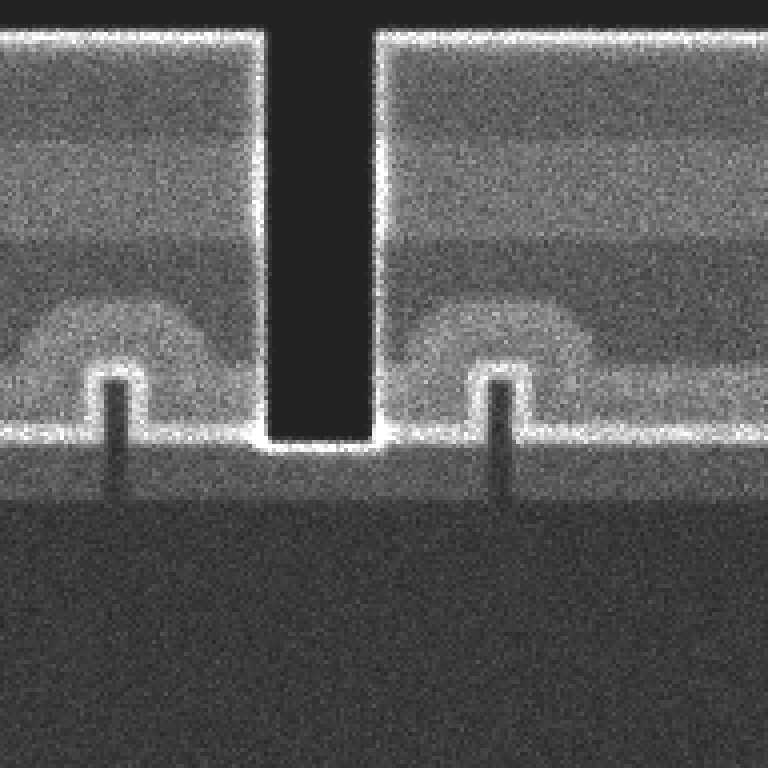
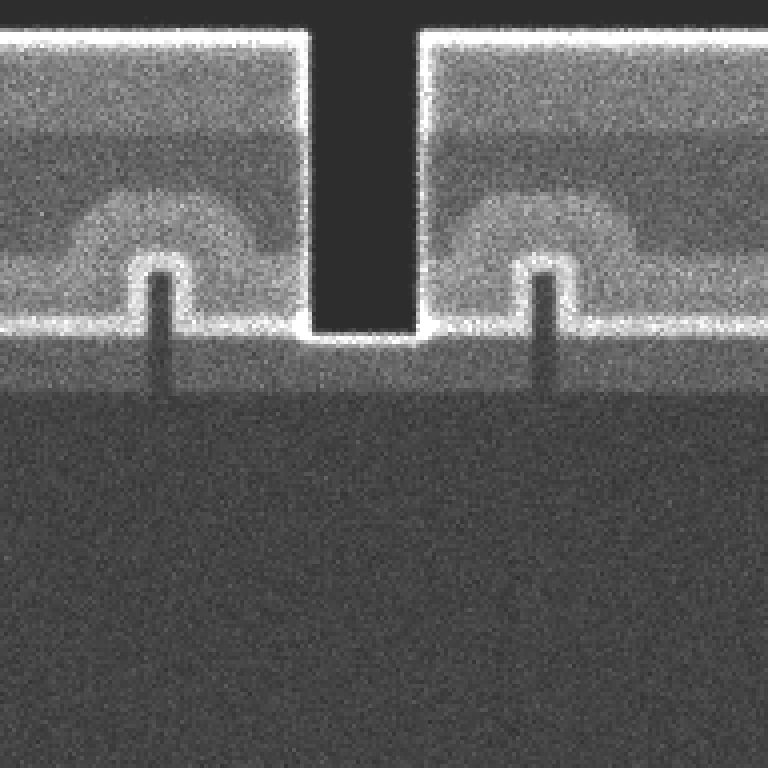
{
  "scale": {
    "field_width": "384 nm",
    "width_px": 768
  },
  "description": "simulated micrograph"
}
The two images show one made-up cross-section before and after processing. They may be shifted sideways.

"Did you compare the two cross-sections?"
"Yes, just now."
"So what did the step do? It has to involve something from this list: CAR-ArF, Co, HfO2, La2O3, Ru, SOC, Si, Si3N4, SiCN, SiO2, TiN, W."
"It removed SOC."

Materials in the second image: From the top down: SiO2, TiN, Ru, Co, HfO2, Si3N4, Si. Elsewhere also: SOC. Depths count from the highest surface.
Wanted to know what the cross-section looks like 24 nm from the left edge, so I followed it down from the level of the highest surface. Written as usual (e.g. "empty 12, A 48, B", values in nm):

SiO2 50, TiN 62, Ru 16, Co 14, HfO2 10, Si3N4 28, Si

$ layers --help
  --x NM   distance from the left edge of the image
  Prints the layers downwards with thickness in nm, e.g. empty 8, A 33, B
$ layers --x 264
SiO2 50, TiN 30, Ru 16, Co 14, HfO2 42, Si3N4 28, Si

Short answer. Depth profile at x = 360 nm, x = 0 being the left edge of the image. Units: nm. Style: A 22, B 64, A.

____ SiO2 50, TiN 62, Ru 16, Co 14, HfO2 10, Si3N4 28, Si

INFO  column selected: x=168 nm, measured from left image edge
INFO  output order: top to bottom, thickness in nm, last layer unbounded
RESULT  empty 152, Si3N4 28, Si